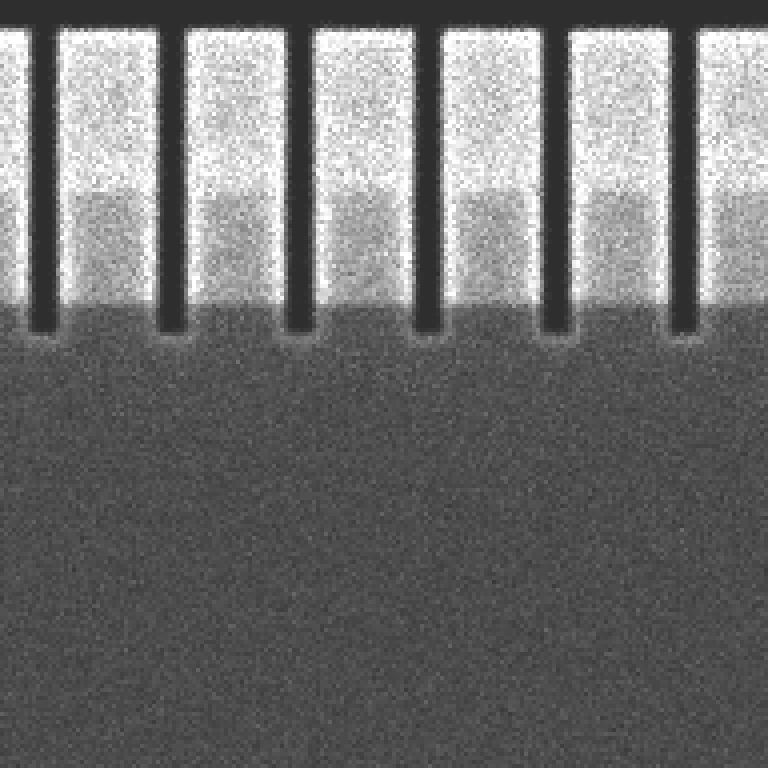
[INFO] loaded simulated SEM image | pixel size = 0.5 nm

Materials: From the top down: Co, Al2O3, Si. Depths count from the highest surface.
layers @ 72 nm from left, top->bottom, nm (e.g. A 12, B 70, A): Co 80, Al2O3 56, Si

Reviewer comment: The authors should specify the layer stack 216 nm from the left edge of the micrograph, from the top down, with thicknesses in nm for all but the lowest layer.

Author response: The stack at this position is empty 152, Si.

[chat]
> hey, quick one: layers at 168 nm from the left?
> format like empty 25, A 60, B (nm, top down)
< Co 80, Al2O3 56, Si